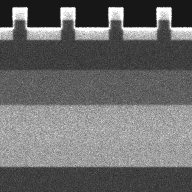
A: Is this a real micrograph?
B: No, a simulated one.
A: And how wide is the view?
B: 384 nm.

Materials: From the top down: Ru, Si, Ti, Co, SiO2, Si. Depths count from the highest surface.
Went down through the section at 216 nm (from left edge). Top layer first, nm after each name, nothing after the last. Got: empty 40, Ru 24, Si 60, Ti 70, Co 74, SiO2 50, Si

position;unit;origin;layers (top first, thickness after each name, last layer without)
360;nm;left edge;empty 40, Ru 24, Si 60, Ti 70, Co 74, SiO2 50, Si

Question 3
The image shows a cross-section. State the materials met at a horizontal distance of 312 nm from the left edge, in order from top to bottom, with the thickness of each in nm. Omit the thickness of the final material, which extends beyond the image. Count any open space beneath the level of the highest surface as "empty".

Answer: empty 40, Ru 24, Si 60, Ti 70, Co 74, SiO2 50, Si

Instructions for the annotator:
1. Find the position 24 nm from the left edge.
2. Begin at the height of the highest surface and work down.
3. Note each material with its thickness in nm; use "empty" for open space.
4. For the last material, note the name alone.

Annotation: empty 40, Ru 24, Si 60, Ti 70, Co 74, SiO2 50, Si